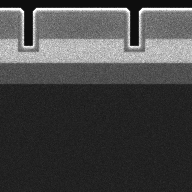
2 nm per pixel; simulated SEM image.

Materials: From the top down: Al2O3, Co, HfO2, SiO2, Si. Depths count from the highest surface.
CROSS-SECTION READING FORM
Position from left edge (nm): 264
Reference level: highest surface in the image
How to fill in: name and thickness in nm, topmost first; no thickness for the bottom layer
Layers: empty 76, Al2O3 12, HfO2 22, SiO2 42, Si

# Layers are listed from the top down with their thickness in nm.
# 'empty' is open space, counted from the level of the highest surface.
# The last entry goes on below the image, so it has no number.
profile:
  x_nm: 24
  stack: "Al2O3 12, Co 50, HfO2 48, SiO2 42, Si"